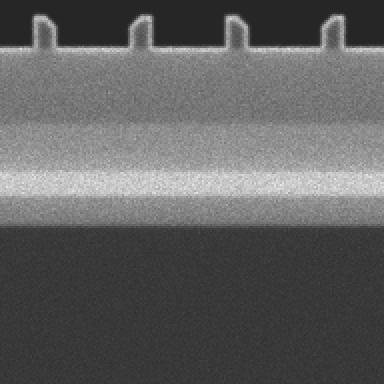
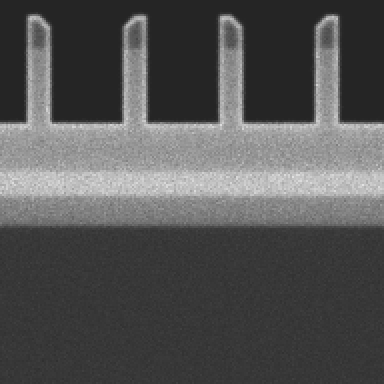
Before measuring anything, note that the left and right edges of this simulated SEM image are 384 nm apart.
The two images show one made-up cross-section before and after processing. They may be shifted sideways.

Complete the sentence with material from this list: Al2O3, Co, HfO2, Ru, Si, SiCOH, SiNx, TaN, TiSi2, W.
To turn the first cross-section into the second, Co must be removed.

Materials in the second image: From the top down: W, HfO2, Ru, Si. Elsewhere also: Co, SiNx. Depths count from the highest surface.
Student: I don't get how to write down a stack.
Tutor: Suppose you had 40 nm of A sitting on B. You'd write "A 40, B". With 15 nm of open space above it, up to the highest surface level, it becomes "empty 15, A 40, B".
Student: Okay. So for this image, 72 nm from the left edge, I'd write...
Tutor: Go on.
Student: empty 108, W 48, HfO2 24, Ru 30, Si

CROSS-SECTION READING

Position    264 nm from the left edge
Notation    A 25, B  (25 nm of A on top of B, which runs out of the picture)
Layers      empty 108, W 48, HfO2 24, Ru 30, Si